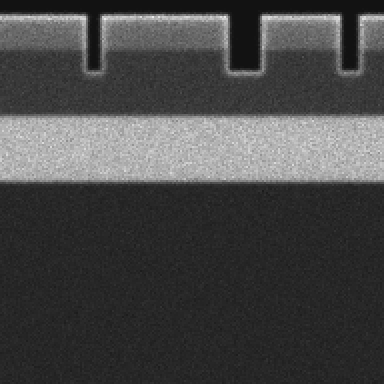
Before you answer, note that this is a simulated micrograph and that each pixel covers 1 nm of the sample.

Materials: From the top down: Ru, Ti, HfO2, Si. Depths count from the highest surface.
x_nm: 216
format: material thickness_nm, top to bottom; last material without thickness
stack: Ru 34, Ti 66, HfO2 66, Si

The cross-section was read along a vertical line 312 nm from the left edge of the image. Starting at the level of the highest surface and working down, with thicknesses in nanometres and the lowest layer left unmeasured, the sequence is Ru 34, Ti 66, HfO2 66, Si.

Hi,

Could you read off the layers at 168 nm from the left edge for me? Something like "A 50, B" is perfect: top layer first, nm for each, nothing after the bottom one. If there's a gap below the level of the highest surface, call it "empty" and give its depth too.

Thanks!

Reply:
Ru 34, Ti 66, HfO2 66, Si